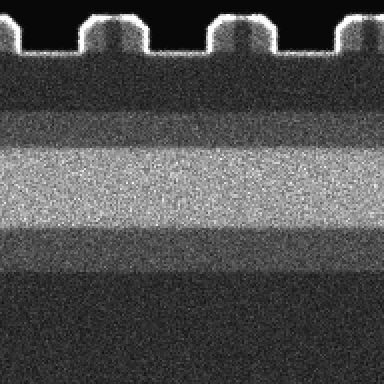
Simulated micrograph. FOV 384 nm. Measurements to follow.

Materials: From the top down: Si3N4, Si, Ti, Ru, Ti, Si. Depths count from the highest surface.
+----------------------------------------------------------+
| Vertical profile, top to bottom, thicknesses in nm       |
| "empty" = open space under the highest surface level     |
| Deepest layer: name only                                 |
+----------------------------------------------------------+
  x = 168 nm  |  empty 36, Si 60, Ti 36, Ru 80, Ti 44, Si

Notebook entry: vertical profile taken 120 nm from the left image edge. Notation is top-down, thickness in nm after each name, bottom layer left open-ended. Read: Si 96, Ti 36, Ru 80, Ti 44, Si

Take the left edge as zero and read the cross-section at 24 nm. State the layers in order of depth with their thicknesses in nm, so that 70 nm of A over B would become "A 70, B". empty 36, Si 60, Ti 36, Ru 80, Ti 44, Si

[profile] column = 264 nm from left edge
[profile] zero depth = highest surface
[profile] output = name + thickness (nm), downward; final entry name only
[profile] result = empty 2, Si3N4 34, Si 60, Ti 36, Ru 80, Ti 44, Si